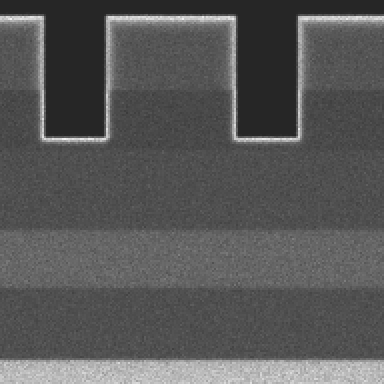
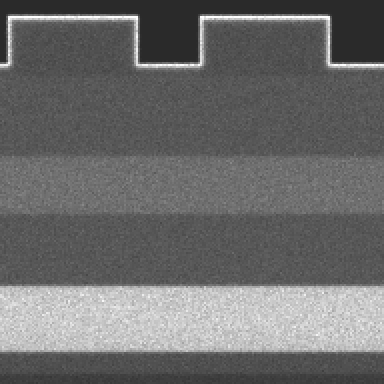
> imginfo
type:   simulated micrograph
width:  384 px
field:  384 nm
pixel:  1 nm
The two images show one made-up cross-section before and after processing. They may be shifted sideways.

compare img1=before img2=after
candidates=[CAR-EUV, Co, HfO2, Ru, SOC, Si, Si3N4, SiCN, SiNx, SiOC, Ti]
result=removed:SOC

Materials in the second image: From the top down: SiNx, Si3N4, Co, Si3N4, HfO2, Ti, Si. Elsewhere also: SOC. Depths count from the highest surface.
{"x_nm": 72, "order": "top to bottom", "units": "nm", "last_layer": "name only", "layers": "SiNx 60, Si3N4 80, Co 58, Si3N4 72, HfO2 66, Ti 22, Si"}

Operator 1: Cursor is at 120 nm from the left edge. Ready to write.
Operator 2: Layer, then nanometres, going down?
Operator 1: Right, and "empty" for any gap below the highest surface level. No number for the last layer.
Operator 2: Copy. SiNx 60, Si3N4 80, Co 58, Si3N4 72, HfO2 66, Ti 22, Si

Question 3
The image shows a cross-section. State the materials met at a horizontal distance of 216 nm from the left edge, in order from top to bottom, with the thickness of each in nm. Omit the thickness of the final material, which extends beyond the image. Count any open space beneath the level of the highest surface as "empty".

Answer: SiNx 60, Si3N4 80, Co 58, Si3N4 72, HfO2 66, Ti 22, Si